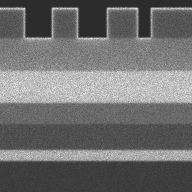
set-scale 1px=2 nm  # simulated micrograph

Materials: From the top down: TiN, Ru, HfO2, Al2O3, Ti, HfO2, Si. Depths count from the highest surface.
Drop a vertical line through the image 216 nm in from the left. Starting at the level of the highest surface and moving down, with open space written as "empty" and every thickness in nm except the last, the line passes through TiN 60, Ru 66, HfO2 64, Al2O3 42, Ti 52, HfO2 22, Si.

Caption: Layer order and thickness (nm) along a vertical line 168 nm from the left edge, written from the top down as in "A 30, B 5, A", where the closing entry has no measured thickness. empty 60, Ru 66, HfO2 64, Al2O3 42, Ti 52, HfO2 22, Si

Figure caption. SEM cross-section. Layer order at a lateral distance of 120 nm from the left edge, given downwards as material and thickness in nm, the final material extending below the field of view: TiN 60, Ru 66, HfO2 64, Al2O3 42, Ti 52, HfO2 22, Si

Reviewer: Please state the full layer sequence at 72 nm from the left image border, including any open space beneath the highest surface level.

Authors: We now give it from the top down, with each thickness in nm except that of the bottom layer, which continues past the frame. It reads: empty 60, Ru 66, HfO2 64, Al2O3 42, Ti 52, HfO2 22, Si